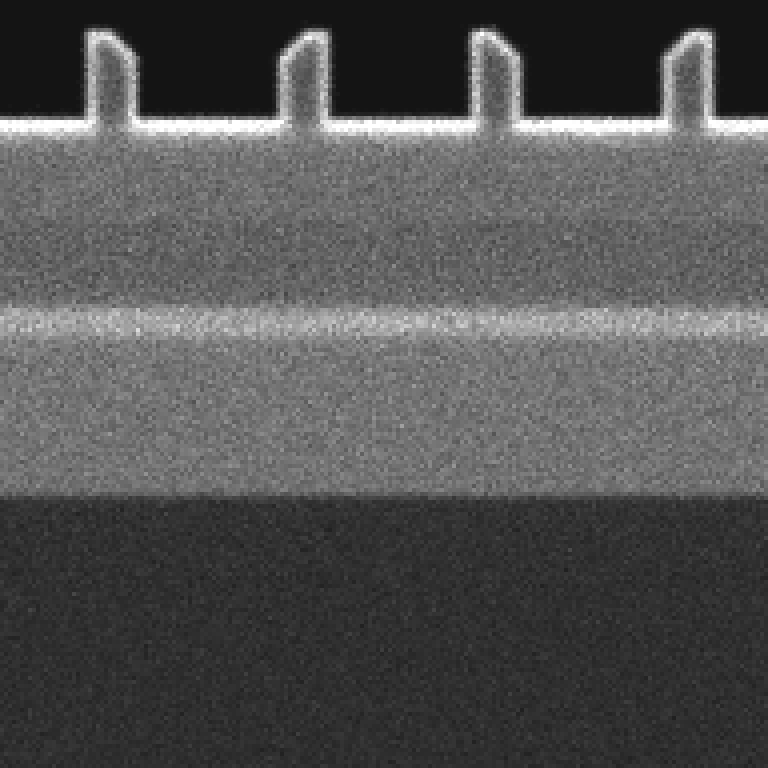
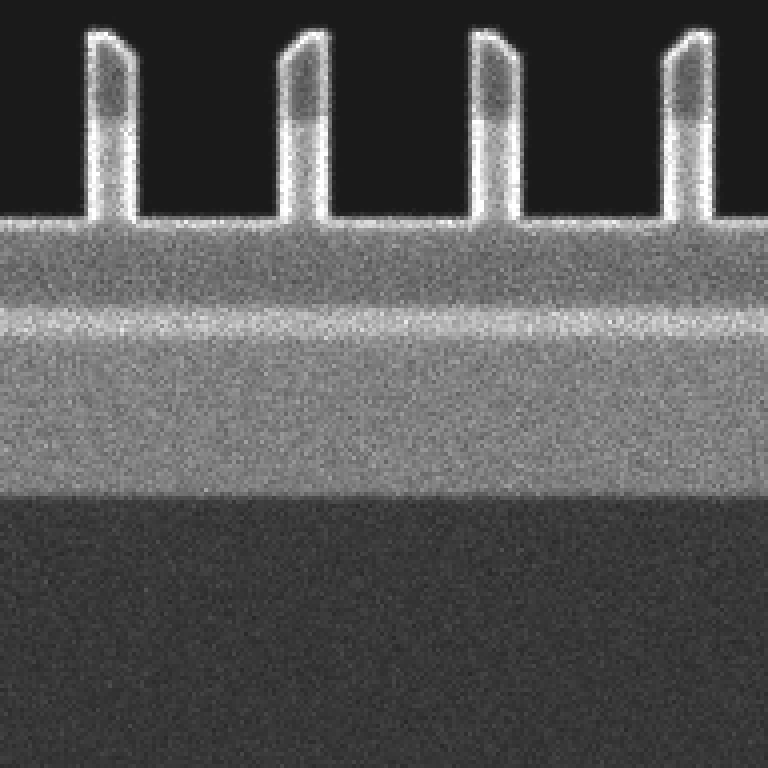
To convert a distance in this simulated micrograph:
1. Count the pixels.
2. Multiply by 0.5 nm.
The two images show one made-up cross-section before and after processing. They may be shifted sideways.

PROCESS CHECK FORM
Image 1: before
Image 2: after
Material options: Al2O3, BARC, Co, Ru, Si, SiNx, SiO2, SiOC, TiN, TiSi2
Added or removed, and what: removed, SiO2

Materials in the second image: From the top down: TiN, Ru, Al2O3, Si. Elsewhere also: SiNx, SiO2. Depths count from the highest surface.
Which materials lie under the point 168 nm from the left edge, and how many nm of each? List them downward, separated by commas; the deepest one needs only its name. empty 94, TiN 44, Ru 14, Al2O3 80, Si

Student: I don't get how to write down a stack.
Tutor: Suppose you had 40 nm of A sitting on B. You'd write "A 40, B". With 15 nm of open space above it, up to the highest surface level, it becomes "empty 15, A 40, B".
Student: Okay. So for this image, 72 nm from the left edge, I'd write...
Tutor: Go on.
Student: empty 94, TiN 44, Ru 14, Al2O3 80, Si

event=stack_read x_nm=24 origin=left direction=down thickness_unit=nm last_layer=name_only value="empty 94, TiN 44, Ru 14, Al2O3 80, Si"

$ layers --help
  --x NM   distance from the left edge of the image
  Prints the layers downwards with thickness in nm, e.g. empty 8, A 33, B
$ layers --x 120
empty 94, TiN 44, Ru 14, Al2O3 80, Si